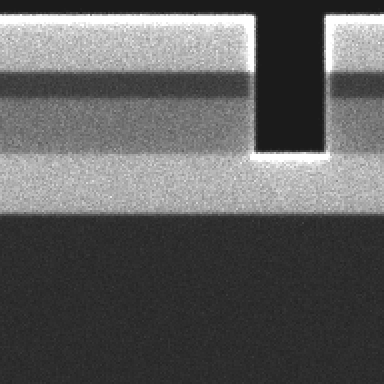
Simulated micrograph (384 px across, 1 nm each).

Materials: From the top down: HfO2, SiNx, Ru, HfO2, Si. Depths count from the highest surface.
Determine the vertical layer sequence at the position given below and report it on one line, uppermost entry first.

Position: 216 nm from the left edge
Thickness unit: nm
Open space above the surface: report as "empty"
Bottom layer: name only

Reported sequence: HfO2 56, SiNx 26, Ru 56, HfO2 60, Si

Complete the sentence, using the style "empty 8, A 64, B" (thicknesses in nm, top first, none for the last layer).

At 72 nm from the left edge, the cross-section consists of HfO2 56, SiNx 26, Ru 56, HfO2 60, Si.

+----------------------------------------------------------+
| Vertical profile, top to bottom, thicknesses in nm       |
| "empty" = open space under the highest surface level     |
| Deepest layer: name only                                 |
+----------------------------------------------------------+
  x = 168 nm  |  HfO2 56, SiNx 26, Ru 56, HfO2 60, Si